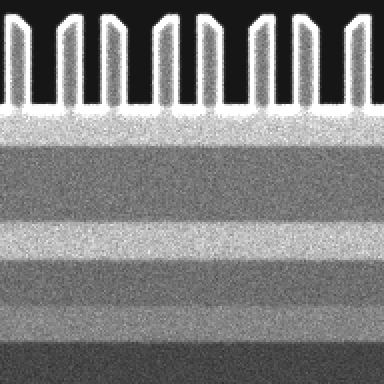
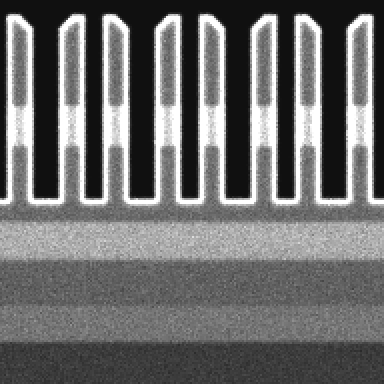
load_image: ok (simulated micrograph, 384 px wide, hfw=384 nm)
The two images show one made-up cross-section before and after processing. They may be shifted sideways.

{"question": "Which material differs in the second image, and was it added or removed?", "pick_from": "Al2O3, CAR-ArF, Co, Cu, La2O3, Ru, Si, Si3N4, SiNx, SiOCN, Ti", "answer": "Al2O3 and SiNx, removed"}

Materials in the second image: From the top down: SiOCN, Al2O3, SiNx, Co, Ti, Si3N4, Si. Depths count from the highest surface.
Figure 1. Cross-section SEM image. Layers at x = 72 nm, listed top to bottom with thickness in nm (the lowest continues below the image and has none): SiOCN 90, Al2O3 40, SiNx 76, Co 38, Ti 46, Si3N4 36, Si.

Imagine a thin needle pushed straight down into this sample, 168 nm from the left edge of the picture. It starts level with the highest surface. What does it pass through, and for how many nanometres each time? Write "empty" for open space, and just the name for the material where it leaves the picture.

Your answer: SiOCN 90, Al2O3 40, SiNx 76, Co 38, Ti 46, Si3N4 36, Si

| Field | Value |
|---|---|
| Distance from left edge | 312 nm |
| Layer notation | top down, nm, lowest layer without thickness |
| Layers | empty 6, SiOCN 84, Al2O3 40, SiNx 76, Co 38, Ti 46, Si3N4 36, Si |